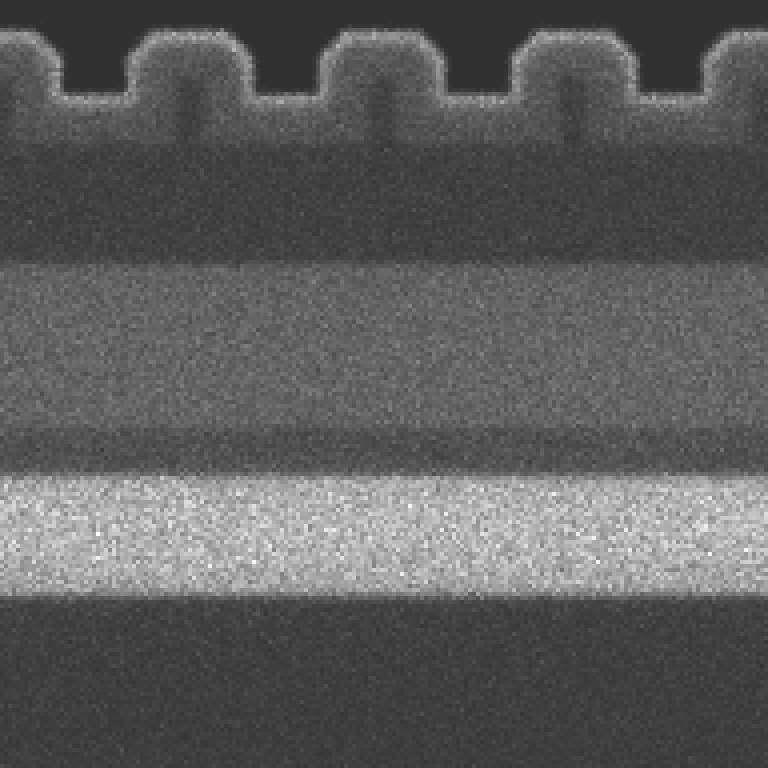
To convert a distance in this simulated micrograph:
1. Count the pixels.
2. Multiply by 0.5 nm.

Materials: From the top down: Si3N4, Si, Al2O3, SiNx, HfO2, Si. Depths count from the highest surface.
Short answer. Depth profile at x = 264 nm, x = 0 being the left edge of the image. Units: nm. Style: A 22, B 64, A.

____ empty 4, Si3N4 52, Si 60, Al2O3 82, SiNx 24, HfO2 60, Si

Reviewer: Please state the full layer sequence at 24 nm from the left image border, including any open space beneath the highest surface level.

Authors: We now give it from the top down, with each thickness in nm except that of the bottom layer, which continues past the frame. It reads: empty 8, Si3N4 48, Si 60, Al2O3 82, SiNx 24, HfO2 60, Si